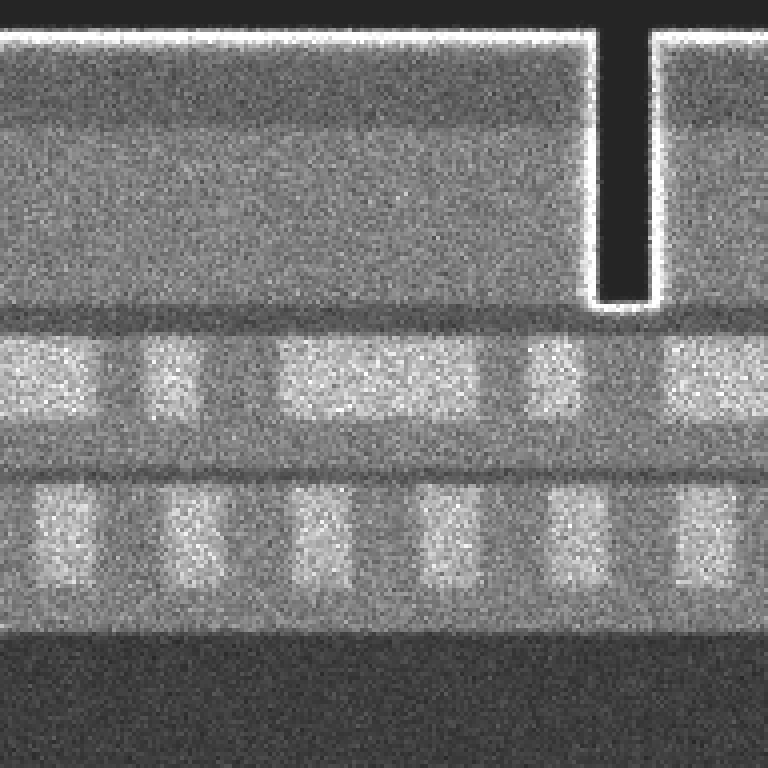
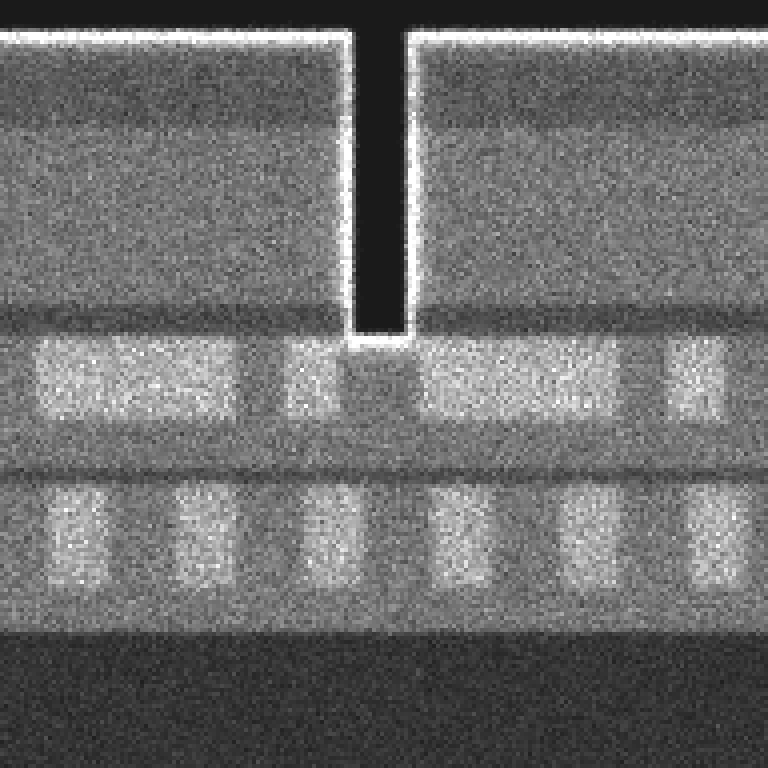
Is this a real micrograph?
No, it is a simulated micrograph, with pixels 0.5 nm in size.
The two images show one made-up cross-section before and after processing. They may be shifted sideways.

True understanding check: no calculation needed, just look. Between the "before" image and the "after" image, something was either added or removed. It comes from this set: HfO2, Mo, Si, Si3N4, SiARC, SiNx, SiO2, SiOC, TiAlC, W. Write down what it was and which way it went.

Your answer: SiNx (removed)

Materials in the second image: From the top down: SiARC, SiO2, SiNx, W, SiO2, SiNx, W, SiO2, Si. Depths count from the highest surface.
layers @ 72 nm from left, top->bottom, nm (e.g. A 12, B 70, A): SiARC 48, SiO2 88, SiNx 16, W 42, SiO2 24, SiNx 8, SiO2 74, Si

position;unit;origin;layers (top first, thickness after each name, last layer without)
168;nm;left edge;SiARC 48, SiO2 88, SiNx 16, W 42, SiO2 24, SiNx 8, W 52, SiO2 22, Si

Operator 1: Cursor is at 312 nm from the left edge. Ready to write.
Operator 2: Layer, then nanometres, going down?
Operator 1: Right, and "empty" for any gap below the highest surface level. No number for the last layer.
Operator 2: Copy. SiARC 48, SiO2 88, SiNx 16, SiO2 66, SiNx 8, SiO2 74, Si